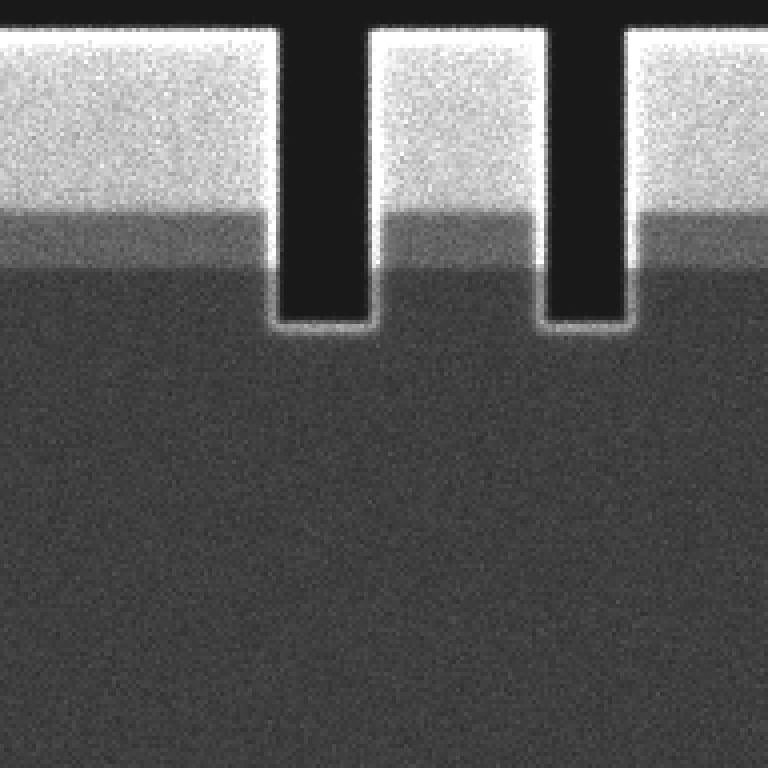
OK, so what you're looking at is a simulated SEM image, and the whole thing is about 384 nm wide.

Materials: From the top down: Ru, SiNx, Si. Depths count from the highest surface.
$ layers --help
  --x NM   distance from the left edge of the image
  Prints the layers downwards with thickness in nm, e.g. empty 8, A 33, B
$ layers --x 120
Ru 90, SiNx 28, Si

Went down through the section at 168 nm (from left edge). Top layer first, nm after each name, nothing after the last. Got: empty 146, Si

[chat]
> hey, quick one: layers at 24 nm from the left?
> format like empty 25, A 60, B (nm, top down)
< Ru 90, SiNx 28, Si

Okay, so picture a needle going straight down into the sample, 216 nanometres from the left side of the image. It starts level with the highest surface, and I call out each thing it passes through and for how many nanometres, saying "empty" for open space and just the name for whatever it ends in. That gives Ru 90, SiNx 28, Si